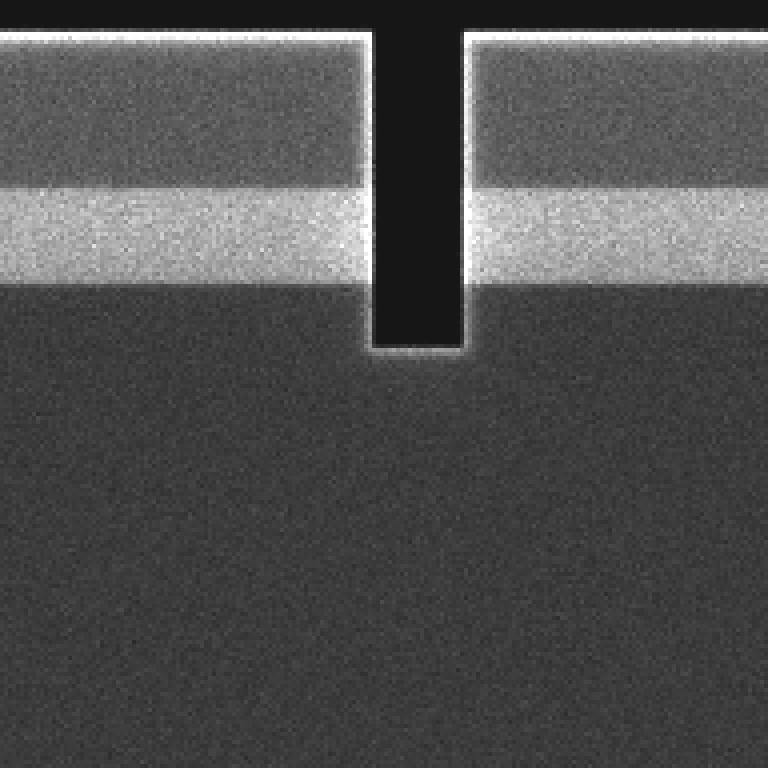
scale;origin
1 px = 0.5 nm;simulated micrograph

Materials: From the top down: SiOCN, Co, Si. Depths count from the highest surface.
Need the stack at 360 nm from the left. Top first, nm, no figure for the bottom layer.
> SiOCN 78, Co 48, Si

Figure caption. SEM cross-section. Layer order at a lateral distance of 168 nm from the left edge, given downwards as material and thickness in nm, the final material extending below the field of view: SiOCN 78, Co 48, Si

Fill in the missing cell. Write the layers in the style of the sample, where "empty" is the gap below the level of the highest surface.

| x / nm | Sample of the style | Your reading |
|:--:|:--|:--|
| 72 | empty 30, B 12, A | SiOCN 78, Co 48, Si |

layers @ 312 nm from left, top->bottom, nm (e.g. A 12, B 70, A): SiOCN 78, Co 48, Si